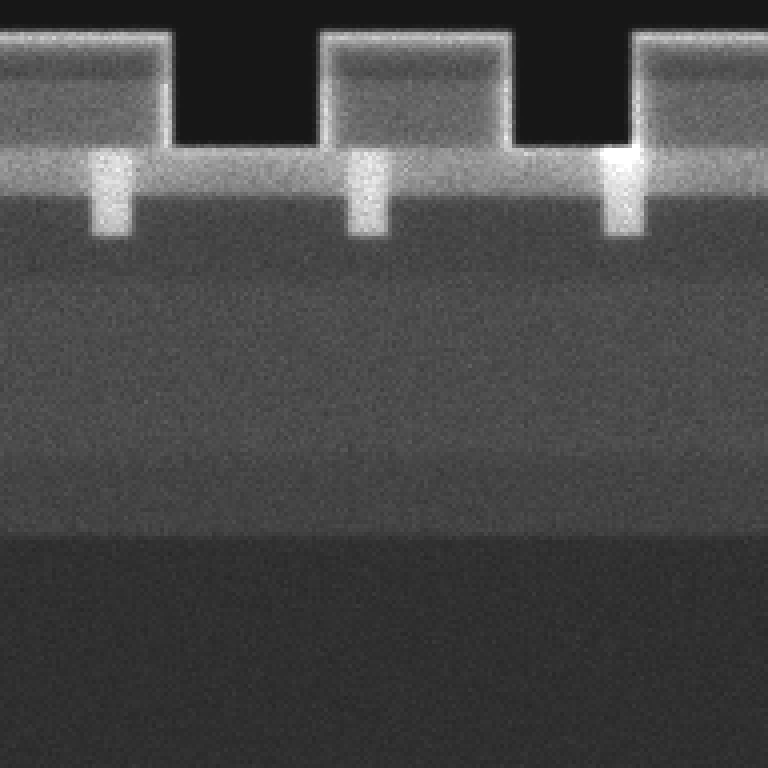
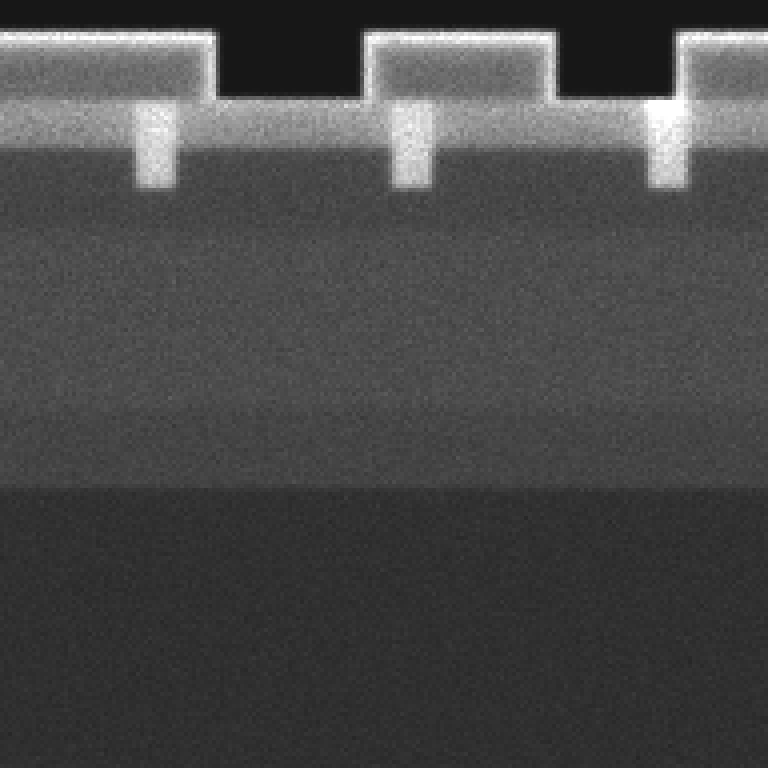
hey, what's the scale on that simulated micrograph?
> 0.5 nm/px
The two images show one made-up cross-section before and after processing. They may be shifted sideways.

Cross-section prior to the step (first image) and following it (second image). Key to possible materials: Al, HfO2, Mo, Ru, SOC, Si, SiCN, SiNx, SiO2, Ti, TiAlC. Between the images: SOC was removed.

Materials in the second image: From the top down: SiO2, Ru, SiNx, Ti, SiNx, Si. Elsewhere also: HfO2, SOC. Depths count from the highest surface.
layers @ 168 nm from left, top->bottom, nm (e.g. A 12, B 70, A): empty 34, Ru 24, SiNx 42, Ti 88, SiNx 40, Si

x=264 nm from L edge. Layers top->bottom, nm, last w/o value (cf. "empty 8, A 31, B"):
SiO2 34, Ru 24, SiNx 42, Ti 88, SiNx 40, Si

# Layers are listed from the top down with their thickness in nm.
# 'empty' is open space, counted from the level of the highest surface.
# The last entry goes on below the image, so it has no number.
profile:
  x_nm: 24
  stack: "SiO2 34, Ru 24, SiNx 42, Ti 88, SiNx 40, Si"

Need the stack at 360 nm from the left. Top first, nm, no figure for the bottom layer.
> SiO2 34, Ru 24, SiNx 42, Ti 88, SiNx 40, Si